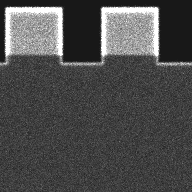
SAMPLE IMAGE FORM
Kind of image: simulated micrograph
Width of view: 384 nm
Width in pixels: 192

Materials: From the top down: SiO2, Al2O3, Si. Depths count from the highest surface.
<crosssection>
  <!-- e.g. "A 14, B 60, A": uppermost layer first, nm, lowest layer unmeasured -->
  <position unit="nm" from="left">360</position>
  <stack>empty 110, Si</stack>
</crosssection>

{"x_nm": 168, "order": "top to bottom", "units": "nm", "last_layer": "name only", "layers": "empty 110, Si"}